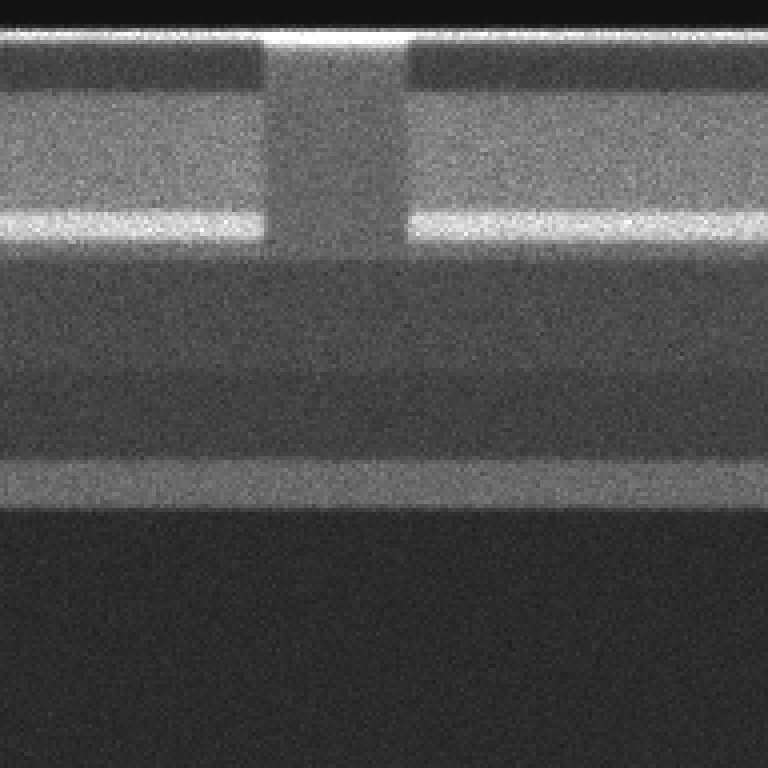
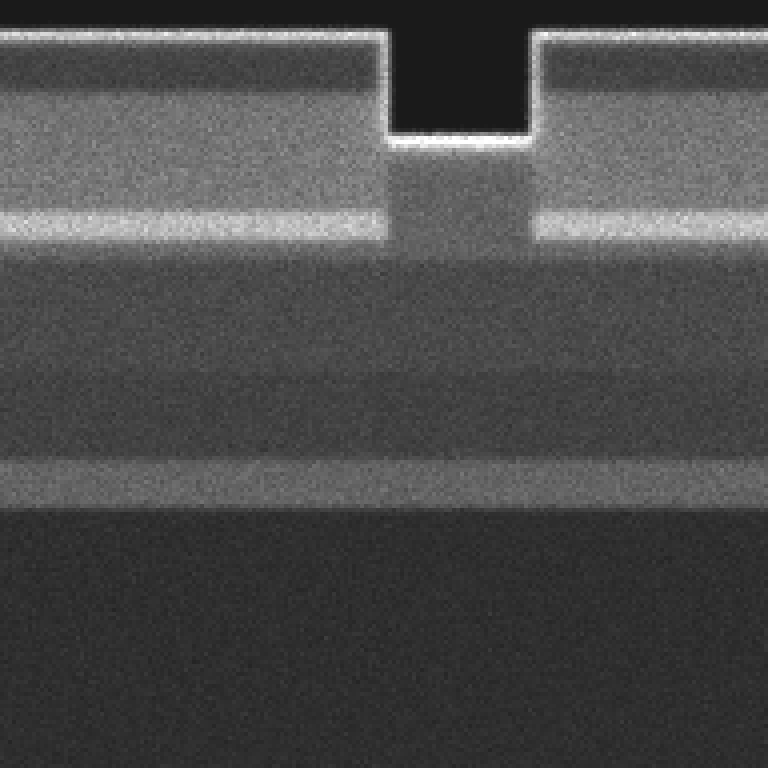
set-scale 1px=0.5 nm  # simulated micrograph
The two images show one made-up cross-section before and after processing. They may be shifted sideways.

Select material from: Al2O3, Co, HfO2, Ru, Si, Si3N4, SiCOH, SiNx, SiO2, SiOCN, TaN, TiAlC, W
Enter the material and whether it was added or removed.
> SiO2 / removed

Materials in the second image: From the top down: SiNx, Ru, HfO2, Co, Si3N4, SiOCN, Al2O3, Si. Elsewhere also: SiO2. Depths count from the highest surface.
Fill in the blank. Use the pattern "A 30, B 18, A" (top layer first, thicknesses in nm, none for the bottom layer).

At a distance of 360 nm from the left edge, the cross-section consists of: SiNx 30, Ru 60, HfO2 14, Co 10, Si3N4 56, SiOCN 44, Al2O3 24, Si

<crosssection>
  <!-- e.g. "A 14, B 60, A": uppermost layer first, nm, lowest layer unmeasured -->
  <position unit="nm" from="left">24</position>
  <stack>SiNx 30, Ru 60, HfO2 14, Co 10, Si3N4 56, SiOCN 44, Al2O3 24, Si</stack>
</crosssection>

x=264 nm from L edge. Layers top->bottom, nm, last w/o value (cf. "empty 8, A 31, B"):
empty 52, SiO2 62, Si3N4 56, SiOCN 44, Al2O3 24, Si